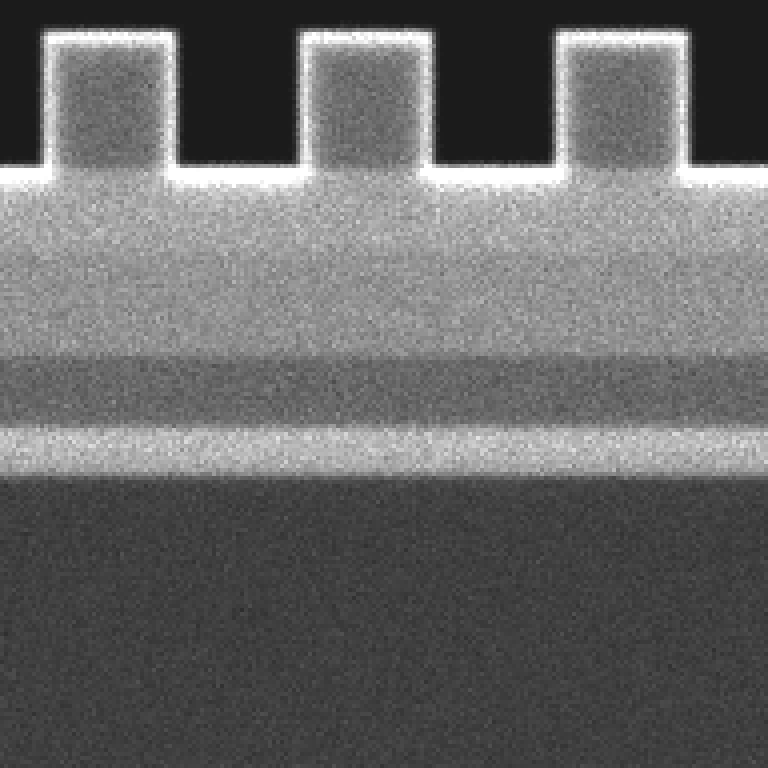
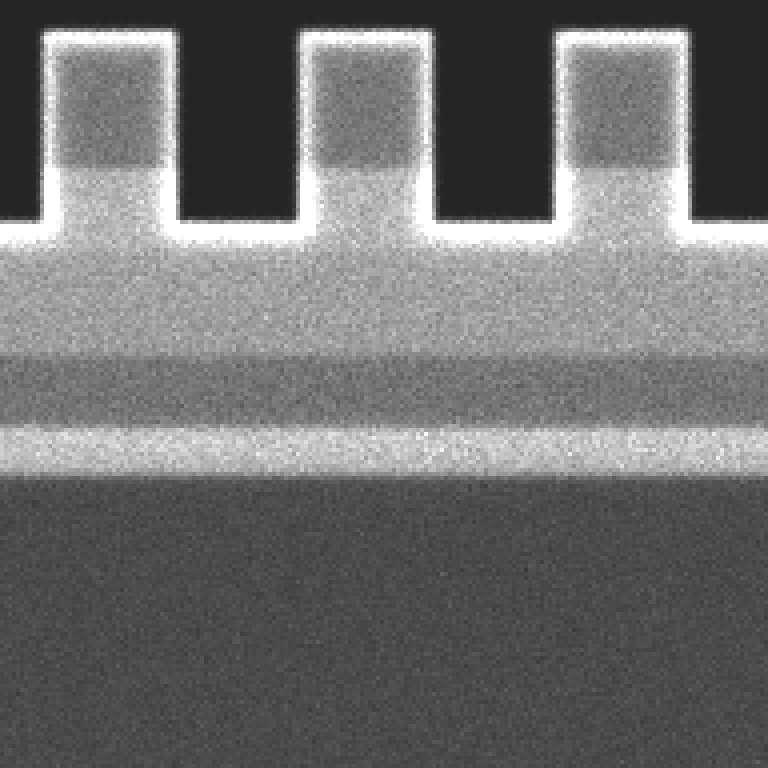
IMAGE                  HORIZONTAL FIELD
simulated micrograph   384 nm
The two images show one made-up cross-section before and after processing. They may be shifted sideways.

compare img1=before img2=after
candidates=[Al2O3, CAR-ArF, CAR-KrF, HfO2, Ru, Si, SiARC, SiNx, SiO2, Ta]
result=removed:Al2O3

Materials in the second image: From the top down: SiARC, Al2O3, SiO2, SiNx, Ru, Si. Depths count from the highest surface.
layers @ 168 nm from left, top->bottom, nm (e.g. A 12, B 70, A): SiARC 68, Al2O3 42, SiO2 52, SiNx 36, Ru 24, Si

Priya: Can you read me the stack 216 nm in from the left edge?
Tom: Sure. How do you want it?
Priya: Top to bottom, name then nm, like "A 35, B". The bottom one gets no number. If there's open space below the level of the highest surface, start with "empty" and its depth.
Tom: empty 96, Al2O3 14, SiO2 52, SiNx 36, Ru 24, Si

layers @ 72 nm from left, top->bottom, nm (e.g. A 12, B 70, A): SiARC 68, Al2O3 42, SiO2 52, SiNx 36, Ru 24, Si